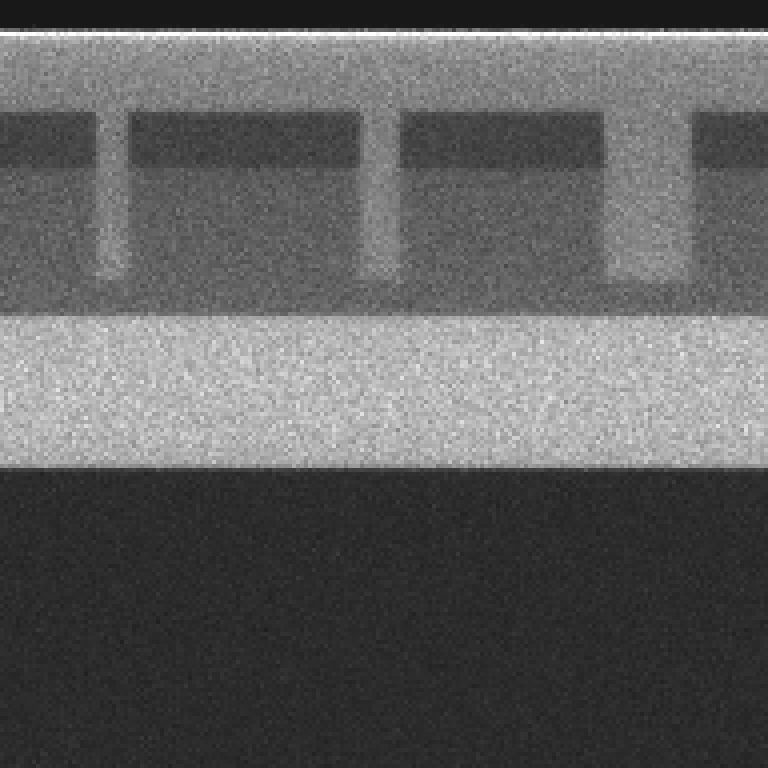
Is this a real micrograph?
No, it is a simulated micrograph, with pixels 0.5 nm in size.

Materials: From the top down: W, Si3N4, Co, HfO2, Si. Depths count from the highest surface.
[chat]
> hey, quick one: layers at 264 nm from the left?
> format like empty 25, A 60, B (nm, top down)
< W 40, Si3N4 28, Co 74, HfO2 76, Si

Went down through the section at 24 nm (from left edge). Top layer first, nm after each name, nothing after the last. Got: W 40, Si3N4 28, Co 74, HfO2 76, Si